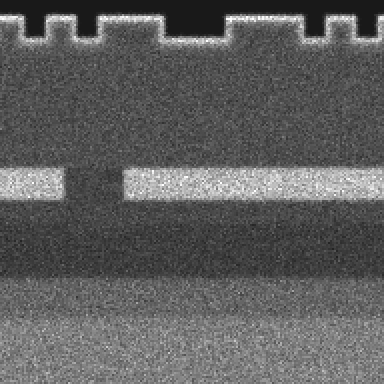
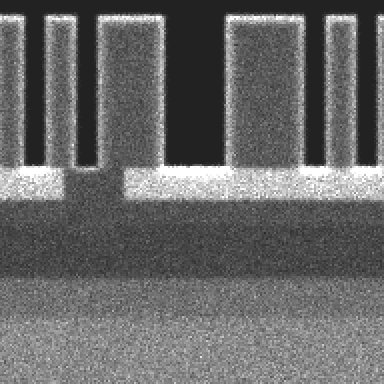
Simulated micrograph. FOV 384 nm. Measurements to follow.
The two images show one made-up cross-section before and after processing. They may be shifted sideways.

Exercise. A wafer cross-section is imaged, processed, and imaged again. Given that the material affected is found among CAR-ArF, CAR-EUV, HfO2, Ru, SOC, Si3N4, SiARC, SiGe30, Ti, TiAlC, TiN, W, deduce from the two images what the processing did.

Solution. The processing removed SOC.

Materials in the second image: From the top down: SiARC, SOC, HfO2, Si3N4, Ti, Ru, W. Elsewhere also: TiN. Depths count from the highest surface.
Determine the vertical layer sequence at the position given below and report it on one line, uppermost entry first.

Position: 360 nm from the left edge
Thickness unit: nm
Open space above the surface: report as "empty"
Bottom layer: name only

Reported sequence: empty 152, HfO2 32, Si3N4 24, Ti 54, Ru 40, W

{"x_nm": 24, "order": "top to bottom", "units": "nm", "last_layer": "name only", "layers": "empty 152, HfO2 32, Si3N4 24, Ti 54, Ru 40, W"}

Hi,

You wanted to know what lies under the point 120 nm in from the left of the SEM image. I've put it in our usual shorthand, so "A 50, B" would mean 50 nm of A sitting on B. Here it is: SiARC 22, SOC 130, TiN 66, Ti 44, Ru 40, W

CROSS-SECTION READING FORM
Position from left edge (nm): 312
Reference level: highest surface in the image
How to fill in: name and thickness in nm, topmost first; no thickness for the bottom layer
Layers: empty 152, HfO2 32, Si3N4 24, Ti 54, Ru 40, W